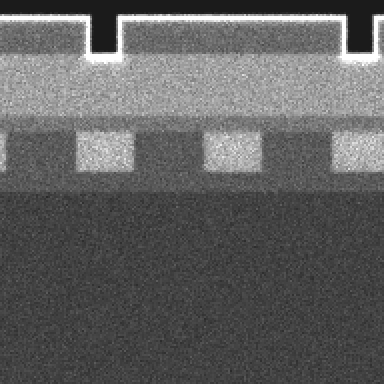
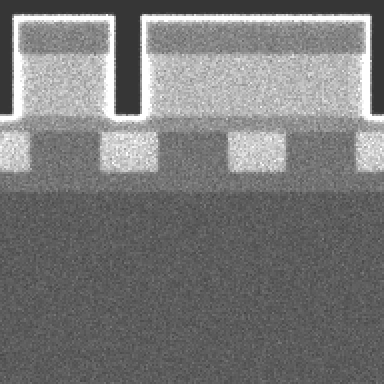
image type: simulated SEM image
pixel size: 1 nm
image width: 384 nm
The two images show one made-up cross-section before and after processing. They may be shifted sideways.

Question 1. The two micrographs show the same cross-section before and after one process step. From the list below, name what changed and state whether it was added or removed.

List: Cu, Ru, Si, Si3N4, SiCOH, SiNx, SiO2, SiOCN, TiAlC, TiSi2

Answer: SiO2, removed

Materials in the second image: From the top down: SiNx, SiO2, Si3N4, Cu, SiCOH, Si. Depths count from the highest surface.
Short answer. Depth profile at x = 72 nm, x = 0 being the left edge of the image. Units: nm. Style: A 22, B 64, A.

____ SiNx 38, SiO2 62, Si3N4 16, SiCOH 60, Si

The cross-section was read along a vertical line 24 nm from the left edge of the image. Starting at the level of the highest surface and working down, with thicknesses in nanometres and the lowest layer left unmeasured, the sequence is SiNx 38, SiO2 62, Si3N4 16, Cu 40, SiCOH 20, Si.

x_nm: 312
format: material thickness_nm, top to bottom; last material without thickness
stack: SiNx 38, SiO2 62, Si3N4 16, SiCOH 60, Si